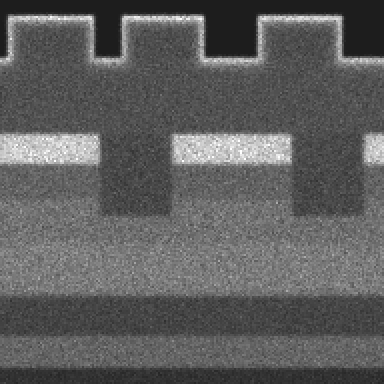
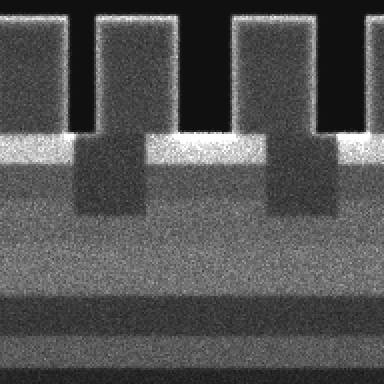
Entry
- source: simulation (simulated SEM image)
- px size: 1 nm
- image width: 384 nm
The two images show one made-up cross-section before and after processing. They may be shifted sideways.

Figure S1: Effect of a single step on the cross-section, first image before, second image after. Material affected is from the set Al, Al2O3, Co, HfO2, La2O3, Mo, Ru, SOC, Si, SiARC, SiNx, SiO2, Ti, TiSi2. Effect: removed SOC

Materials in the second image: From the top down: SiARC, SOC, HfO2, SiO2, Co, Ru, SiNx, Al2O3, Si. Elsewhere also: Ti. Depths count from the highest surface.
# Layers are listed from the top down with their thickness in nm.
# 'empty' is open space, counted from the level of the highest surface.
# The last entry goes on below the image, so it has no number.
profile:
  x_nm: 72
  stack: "empty 118, HfO2 30, SiO2 36, Co 44, Ru 52, SiNx 40, Al2O3 32, Si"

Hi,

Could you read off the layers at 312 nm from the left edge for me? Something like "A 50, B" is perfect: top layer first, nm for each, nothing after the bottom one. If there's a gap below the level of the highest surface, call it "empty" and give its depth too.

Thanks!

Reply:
SiARC 42, SOC 76, Ti 82, Co 28, Ru 52, SiNx 40, Al2O3 32, Si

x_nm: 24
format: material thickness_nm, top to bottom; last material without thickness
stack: SiARC 42, SOC 76, HfO2 30, SiO2 36, Co 44, Ru 52, SiNx 40, Al2O3 32, Si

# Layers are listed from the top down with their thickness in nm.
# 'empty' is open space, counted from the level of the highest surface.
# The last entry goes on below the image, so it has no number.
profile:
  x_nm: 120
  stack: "SiARC 42, SOC 76, Ti 82, Co 28, Ru 52, SiNx 40, Al2O3 32, Si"